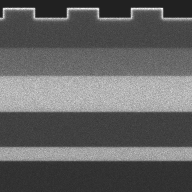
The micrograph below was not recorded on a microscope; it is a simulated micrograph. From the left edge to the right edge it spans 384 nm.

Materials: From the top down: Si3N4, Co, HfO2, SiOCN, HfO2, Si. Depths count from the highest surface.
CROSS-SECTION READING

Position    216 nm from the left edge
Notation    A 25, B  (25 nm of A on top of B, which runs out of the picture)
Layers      empty 20, Si3N4 60, Co 56, HfO2 72, SiOCN 70, HfO2 28, Si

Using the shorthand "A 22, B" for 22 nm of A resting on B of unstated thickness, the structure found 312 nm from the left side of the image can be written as Si3N4 80, Co 56, HfO2 72, SiOCN 70, HfO2 28, Si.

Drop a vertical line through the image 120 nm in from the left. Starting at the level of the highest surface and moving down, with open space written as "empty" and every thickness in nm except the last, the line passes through empty 20, Si3N4 60, Co 56, HfO2 72, SiOCN 70, HfO2 28, Si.